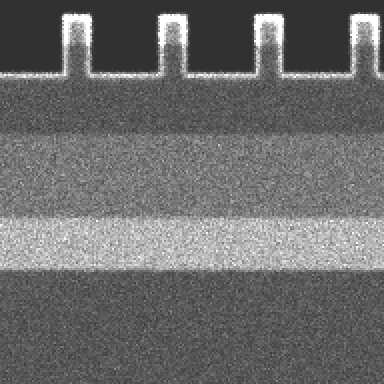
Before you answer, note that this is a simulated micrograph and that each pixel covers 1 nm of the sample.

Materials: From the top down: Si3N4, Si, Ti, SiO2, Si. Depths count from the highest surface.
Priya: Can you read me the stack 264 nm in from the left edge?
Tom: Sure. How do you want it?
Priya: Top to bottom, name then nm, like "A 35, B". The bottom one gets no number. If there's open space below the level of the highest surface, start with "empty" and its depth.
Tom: Si3N4 28, Si 90, Ti 84, SiO2 52, Si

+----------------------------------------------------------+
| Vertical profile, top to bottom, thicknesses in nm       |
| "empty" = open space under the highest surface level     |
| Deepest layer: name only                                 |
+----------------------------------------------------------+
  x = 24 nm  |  empty 58, Si 60, Ti 84, SiO2 52, Si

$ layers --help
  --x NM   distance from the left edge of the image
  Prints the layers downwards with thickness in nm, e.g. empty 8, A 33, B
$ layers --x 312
empty 58, Si 60, Ti 84, SiO2 52, Si